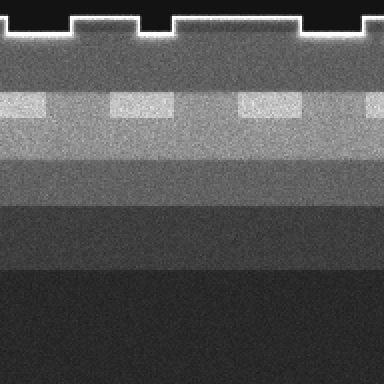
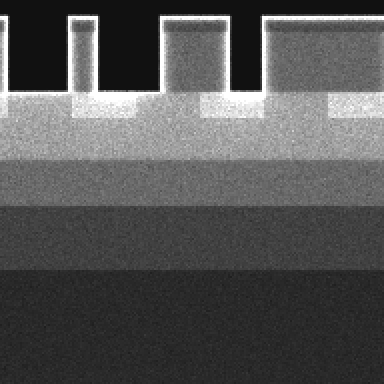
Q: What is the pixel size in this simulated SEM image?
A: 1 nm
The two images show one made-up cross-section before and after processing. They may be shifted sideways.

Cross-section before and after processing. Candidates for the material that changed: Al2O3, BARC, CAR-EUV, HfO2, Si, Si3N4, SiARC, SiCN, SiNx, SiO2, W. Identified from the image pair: SiO2 (removed).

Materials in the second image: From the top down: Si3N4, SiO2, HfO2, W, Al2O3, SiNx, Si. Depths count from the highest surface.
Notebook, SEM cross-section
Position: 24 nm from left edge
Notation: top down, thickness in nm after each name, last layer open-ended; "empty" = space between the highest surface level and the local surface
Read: empty 76, W 68, Al2O3 46, SiNx 64, Si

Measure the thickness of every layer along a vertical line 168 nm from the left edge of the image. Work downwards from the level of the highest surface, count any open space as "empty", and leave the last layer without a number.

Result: Si3N4 16, SiO2 60, W 68, Al2O3 46, SiNx 64, Si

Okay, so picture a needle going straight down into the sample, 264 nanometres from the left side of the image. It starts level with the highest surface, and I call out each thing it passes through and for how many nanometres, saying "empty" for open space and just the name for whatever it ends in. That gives Si3N4 16, SiO2 60, W 68, Al2O3 46, SiNx 64, Si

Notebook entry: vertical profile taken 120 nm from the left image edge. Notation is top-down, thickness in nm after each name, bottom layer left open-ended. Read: empty 76, HfO2 26, W 42, Al2O3 46, SiNx 64, Si